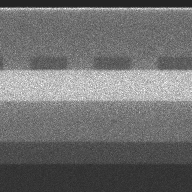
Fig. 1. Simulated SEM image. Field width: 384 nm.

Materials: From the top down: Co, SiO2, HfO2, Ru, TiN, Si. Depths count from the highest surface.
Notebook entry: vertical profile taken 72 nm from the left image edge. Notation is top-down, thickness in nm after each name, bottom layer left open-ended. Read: Co 98, SiO2 26, HfO2 62, Ru 82, TiN 44, Si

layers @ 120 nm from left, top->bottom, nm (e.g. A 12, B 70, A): Co 98, SiO2 26, HfO2 62, Ru 82, TiN 44, Si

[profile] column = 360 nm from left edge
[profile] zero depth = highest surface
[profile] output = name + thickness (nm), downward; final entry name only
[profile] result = Co 98, SiO2 26, HfO2 62, Ru 82, TiN 44, Si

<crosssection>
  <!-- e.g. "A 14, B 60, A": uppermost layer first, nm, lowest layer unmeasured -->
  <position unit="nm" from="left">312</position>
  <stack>Co 124, HfO2 62, Ru 82, TiN 44, Si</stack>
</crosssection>